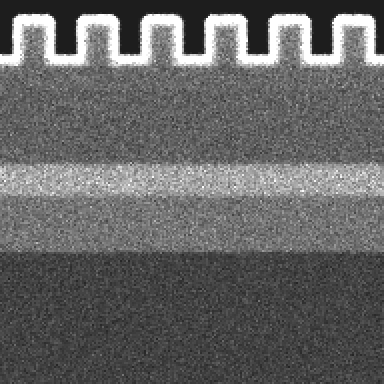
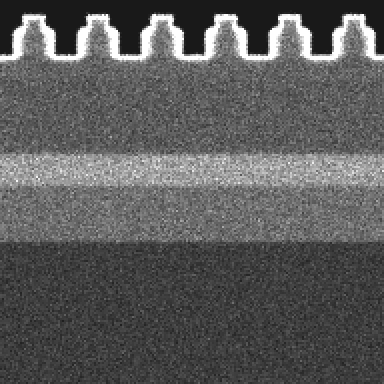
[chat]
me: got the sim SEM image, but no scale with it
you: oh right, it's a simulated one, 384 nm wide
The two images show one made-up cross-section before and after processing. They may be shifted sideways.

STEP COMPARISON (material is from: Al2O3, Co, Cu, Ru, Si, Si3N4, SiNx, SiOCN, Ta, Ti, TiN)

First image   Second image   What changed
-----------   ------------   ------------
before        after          Al2O3, removed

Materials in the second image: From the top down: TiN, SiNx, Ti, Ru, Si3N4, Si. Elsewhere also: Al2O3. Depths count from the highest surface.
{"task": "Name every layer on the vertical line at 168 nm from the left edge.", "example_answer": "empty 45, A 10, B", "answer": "TiN 40, SiNx 24, Ti 74, Ru 32, Si3N4 56, Si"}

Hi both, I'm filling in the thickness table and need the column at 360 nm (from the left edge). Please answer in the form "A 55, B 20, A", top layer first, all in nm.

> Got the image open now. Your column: TiN 40, SiNx 24, Ti 74, Ru 32, Si3N4 56, Si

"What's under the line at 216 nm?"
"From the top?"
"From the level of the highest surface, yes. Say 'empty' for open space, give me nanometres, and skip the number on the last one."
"TiN 40, SiNx 24, Ti 74, Ru 32, Si3N4 56, Si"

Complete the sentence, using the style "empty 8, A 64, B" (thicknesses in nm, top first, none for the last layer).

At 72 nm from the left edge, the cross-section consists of empty 40, SiNx 24, Ti 74, Ru 32, Si3N4 56, Si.